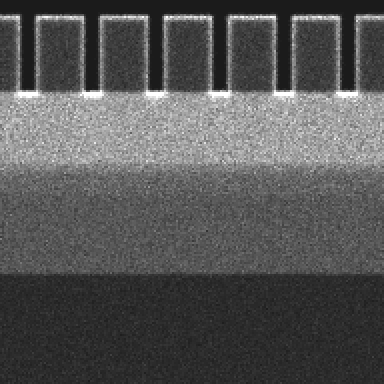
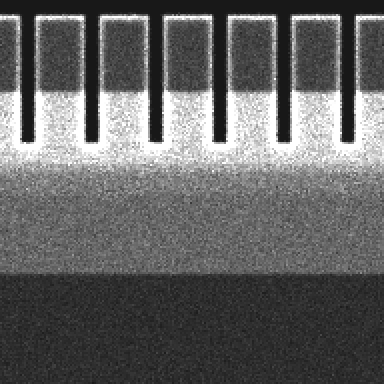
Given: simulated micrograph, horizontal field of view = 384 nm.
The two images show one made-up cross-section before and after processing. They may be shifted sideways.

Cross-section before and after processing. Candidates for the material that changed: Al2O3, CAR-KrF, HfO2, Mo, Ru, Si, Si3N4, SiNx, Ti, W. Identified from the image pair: HfO2 (removed).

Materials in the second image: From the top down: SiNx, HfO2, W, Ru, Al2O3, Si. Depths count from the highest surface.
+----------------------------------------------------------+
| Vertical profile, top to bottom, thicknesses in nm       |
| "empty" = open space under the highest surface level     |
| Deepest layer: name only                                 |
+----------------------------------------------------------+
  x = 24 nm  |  empty 128, HfO2 20, W 8, Ru 24, Al2O3 78, Si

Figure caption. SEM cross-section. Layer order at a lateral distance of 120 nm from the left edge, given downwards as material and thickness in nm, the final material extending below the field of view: SiNx 76, HfO2 72, W 8, Ru 24, Al2O3 78, Si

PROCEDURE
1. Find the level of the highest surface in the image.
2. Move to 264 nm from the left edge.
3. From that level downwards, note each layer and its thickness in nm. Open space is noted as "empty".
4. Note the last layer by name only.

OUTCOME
SiNx 76, HfO2 72, W 8, Ru 24, Al2O3 78, Si